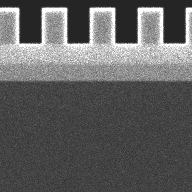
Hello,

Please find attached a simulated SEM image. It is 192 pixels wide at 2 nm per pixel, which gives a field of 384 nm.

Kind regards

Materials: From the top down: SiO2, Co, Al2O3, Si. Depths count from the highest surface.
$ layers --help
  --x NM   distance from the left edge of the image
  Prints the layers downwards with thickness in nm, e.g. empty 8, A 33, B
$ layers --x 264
empty 72, Co 40, Al2O3 34, Si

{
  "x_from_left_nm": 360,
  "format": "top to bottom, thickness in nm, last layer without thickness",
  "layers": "empty 72, Co 40, Al2O3 34, Si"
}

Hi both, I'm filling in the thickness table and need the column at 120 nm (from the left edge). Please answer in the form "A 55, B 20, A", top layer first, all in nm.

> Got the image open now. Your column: SiO2 72, Co 40, Al2O3 34, Si